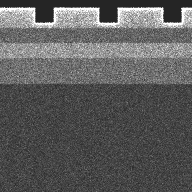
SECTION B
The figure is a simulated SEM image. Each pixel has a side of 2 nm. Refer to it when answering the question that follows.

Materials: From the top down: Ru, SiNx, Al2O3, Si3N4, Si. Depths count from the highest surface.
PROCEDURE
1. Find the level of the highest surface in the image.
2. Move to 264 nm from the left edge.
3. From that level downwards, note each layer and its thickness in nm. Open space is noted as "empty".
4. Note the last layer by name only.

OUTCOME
Ru 40, SiNx 30, Al2O3 30, Si3N4 52, Si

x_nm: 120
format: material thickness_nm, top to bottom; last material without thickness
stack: Ru 40, SiNx 30, Al2O3 30, Si3N4 52, Si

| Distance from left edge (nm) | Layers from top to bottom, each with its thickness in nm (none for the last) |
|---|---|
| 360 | empty 30, Ru 10, SiNx 30, Al2O3 30, Si3N4 52, Si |